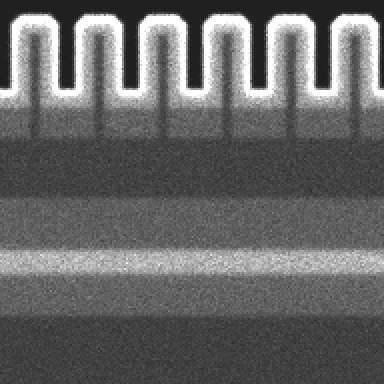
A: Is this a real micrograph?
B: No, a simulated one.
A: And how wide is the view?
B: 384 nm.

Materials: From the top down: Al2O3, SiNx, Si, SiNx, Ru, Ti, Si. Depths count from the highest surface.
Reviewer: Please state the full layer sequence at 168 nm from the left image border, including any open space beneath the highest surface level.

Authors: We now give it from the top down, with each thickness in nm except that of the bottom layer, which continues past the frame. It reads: Al2O3 92, SiNx 30, Si 60, SiNx 52, Ru 24, Ti 42, Si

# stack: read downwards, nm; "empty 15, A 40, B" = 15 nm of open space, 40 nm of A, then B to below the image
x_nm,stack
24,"Al2O3 92, SiNx 30, Si 60, SiNx 52, Ru 24, Ti 42, Si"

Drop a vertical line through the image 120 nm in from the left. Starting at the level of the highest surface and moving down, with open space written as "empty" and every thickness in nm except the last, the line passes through empty 8, Al2O3 84, SiNx 30, Si 60, SiNx 52, Ru 24, Ti 42, Si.